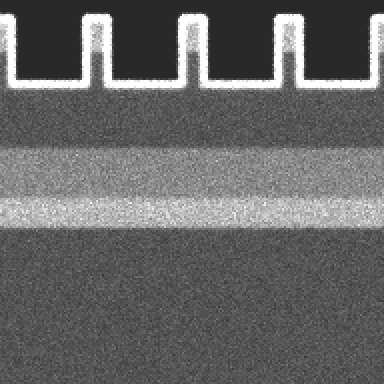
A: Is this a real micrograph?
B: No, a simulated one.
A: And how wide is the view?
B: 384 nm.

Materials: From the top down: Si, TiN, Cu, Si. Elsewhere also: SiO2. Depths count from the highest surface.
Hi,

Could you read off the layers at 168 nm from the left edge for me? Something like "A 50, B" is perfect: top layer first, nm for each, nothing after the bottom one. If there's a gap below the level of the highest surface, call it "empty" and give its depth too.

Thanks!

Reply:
empty 66, Si 66, TiN 50, Cu 30, Si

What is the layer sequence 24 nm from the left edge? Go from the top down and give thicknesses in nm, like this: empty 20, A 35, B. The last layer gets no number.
empty 66, Si 66, TiN 50, Cu 30, Si